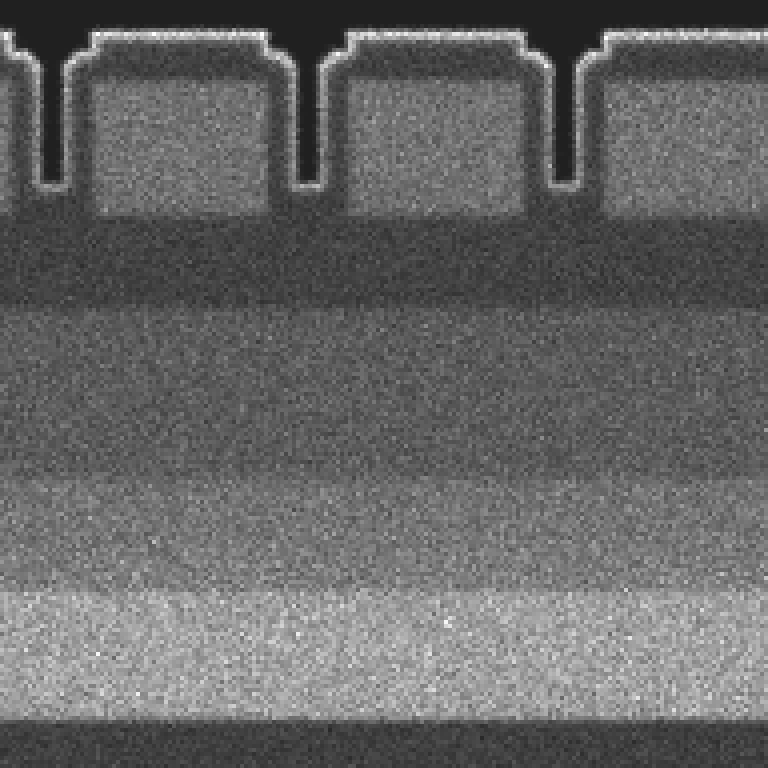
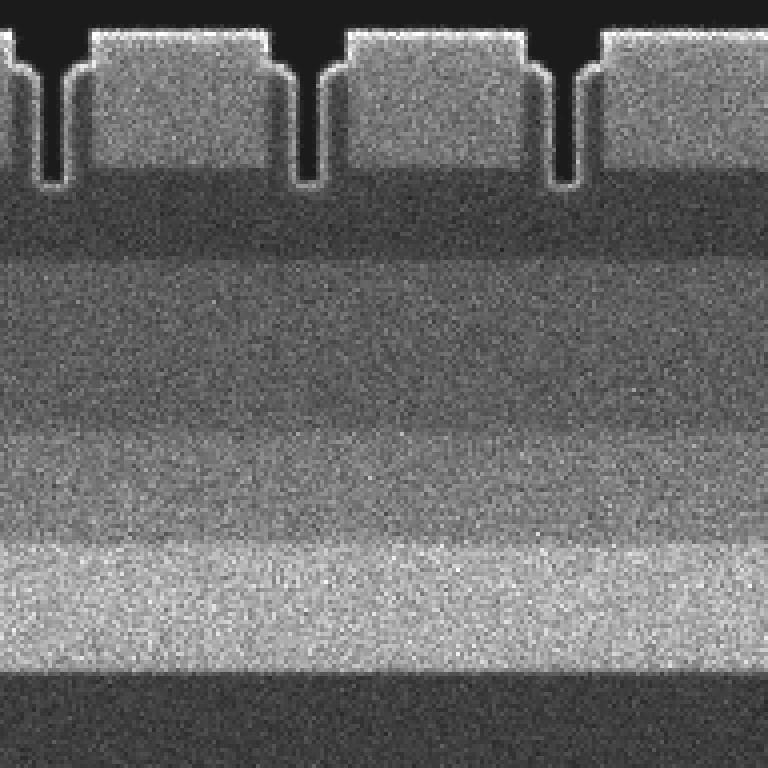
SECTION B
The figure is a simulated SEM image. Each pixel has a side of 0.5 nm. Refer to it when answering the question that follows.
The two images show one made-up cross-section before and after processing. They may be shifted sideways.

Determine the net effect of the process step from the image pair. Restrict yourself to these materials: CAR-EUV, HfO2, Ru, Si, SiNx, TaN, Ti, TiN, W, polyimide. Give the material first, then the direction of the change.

SiNx: removed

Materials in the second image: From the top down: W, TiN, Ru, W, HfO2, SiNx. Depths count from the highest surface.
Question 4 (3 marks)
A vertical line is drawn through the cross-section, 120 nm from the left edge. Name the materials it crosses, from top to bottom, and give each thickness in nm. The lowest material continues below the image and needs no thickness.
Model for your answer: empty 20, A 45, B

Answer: W 68, TiN 46, Ru 86, W 56, HfO2 64, SiNx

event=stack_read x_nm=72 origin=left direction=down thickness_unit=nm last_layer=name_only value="W 68, TiN 46, Ru 86, W 56, HfO2 64, SiNx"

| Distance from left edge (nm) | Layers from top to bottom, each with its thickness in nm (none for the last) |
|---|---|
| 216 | W 68, TiN 46, Ru 86, W 56, HfO2 64, SiNx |